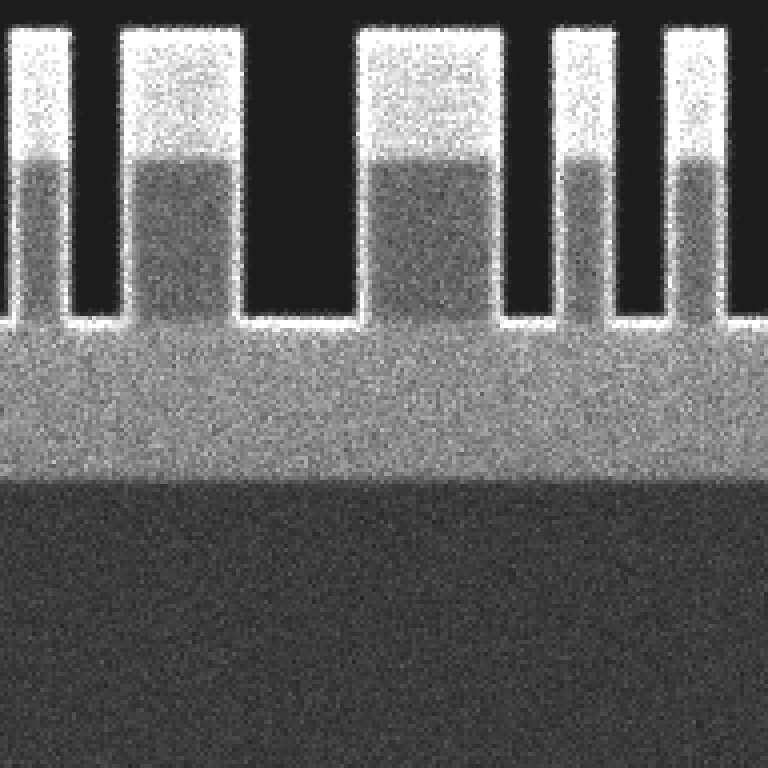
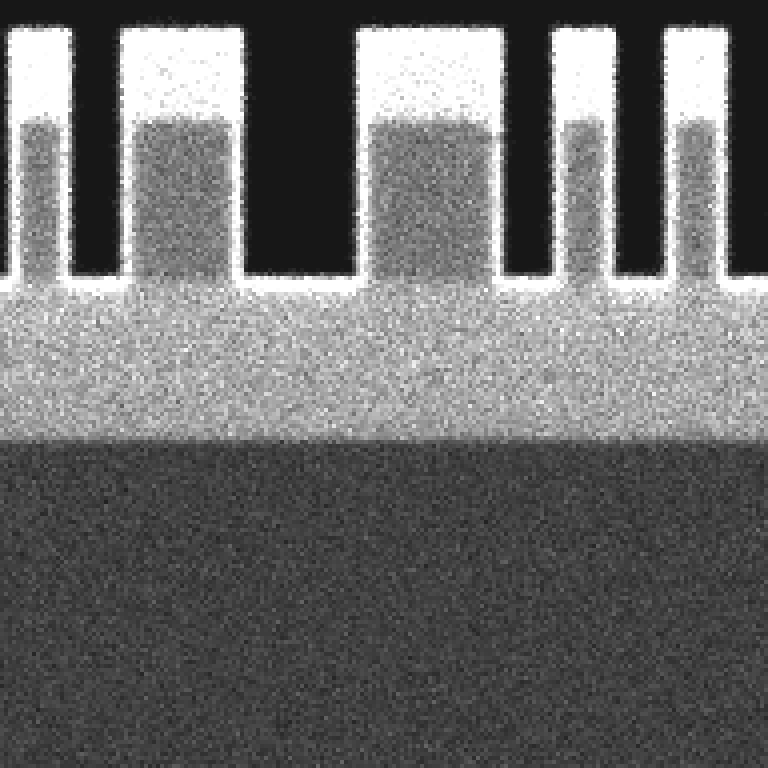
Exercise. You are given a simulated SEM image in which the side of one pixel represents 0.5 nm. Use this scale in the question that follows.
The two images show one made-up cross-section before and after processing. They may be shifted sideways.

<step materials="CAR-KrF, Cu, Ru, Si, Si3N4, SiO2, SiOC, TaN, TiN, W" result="removed W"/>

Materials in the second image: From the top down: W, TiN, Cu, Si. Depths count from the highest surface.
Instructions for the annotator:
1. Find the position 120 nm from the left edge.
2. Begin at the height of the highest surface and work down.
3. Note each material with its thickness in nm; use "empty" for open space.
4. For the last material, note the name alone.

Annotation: empty 124, Cu 80, Si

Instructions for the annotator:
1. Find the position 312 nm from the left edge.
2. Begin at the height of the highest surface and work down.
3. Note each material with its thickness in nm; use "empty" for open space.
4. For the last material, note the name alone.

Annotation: empty 124, Cu 80, Si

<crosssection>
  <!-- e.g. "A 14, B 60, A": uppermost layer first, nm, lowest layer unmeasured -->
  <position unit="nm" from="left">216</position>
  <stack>W 44, TiN 80, Cu 80, Si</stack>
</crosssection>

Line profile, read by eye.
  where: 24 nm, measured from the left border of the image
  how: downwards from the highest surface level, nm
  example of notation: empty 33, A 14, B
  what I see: W 44, TiN 80, Cu 80, Si